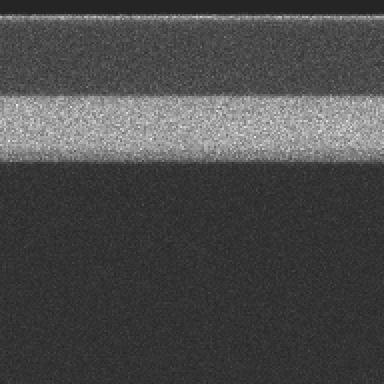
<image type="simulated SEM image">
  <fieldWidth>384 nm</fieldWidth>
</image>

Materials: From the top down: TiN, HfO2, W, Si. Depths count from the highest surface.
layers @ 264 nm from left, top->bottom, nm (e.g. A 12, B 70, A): TiN 80, HfO2 54, W 12, Si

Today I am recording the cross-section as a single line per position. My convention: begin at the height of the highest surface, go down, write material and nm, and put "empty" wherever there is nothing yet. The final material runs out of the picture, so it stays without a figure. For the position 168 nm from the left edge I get TiN 80, HfO2 54, W 12, Si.